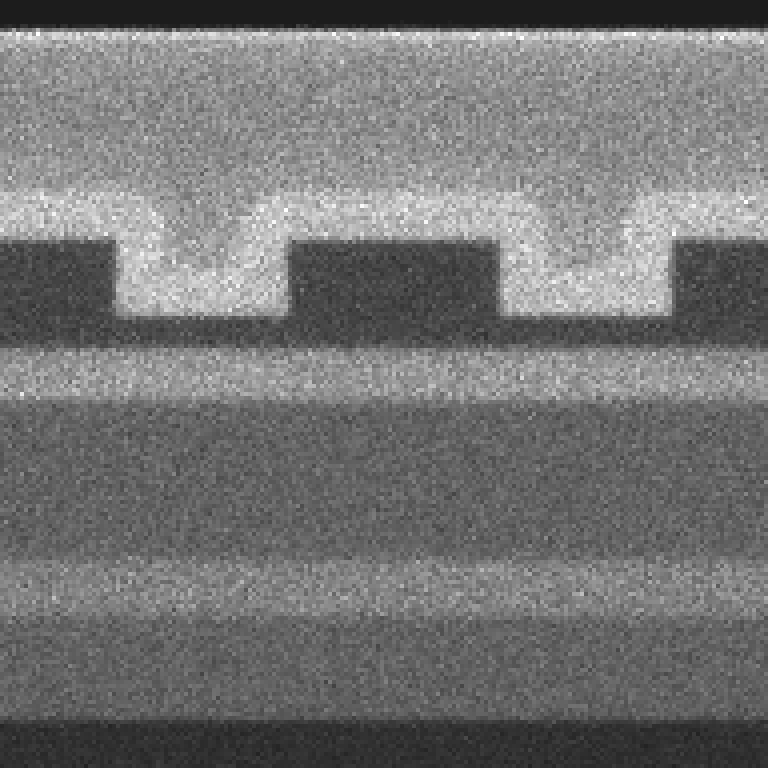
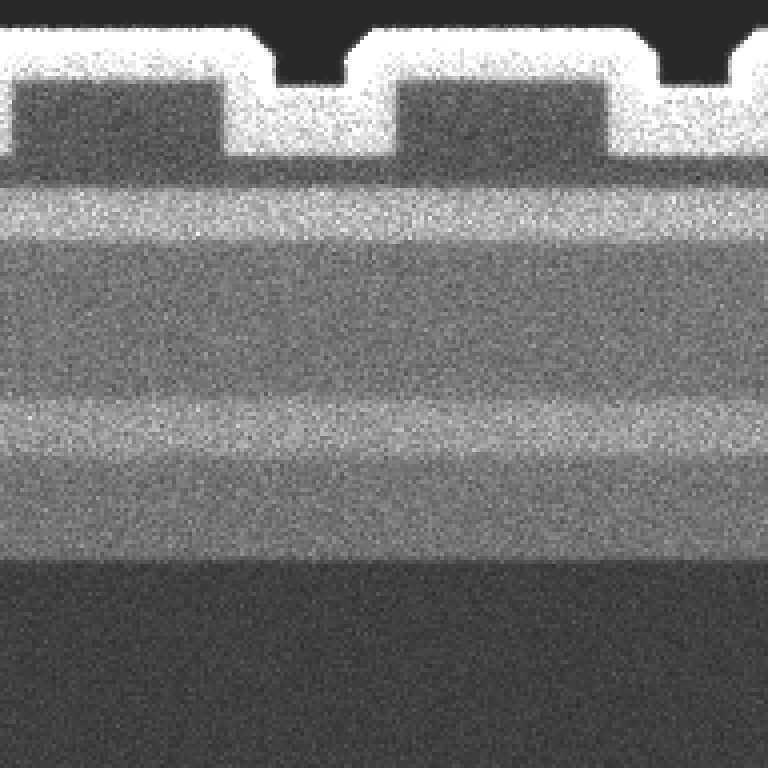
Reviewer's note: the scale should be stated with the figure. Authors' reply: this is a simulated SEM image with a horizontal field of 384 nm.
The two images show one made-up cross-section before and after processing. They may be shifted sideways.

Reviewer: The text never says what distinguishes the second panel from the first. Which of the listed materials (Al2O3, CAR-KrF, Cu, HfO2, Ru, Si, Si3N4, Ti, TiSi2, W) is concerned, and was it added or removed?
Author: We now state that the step removed W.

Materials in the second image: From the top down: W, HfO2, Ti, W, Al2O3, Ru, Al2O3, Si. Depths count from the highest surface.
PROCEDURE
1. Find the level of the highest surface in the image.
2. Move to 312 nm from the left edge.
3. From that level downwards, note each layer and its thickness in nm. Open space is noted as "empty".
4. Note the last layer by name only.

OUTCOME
HfO2 62, Ti 16, W 26, Al2O3 80, Ru 28, Al2O3 52, Si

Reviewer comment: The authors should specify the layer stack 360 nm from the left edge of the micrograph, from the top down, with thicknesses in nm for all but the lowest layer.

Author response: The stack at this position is empty 28, W 10, HfO2 24, Ti 16, W 26, Al2O3 80, Ru 28, Al2O3 52, Si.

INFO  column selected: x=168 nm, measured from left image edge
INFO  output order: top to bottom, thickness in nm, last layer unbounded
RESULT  empty 28, W 10, HfO2 24, Ti 16, W 26, Al2O3 80, Ru 28, Al2O3 52, Si